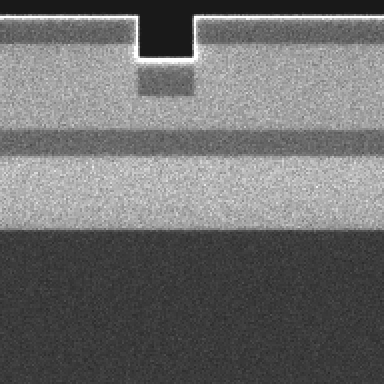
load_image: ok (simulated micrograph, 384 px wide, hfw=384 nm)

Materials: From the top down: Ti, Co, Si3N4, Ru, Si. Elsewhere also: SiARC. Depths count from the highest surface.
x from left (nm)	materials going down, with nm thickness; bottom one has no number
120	Ti 28, Co 86, Si3N4 26, Ru 74, Si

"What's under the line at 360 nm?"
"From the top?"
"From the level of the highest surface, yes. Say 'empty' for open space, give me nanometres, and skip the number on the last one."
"Ti 28, Co 86, Si3N4 26, Ru 74, Si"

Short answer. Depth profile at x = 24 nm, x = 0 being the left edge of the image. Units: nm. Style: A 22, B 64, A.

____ Ti 28, Co 86, Si3N4 26, Ru 74, Si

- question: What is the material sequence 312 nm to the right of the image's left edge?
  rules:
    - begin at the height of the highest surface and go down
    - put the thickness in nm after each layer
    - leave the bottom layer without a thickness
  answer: Ti 28, Co 86, Si3N4 26, Ru 74, Si